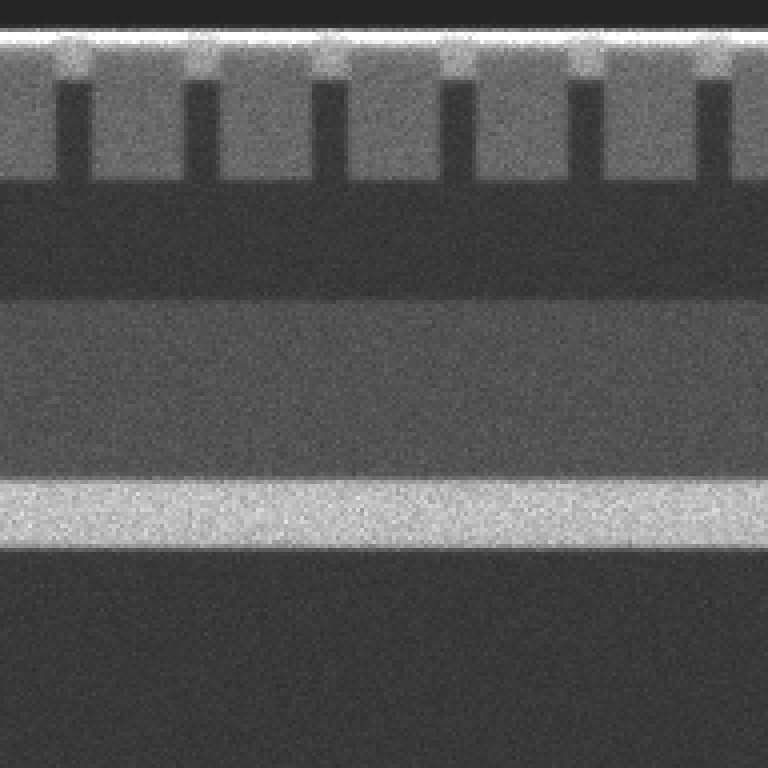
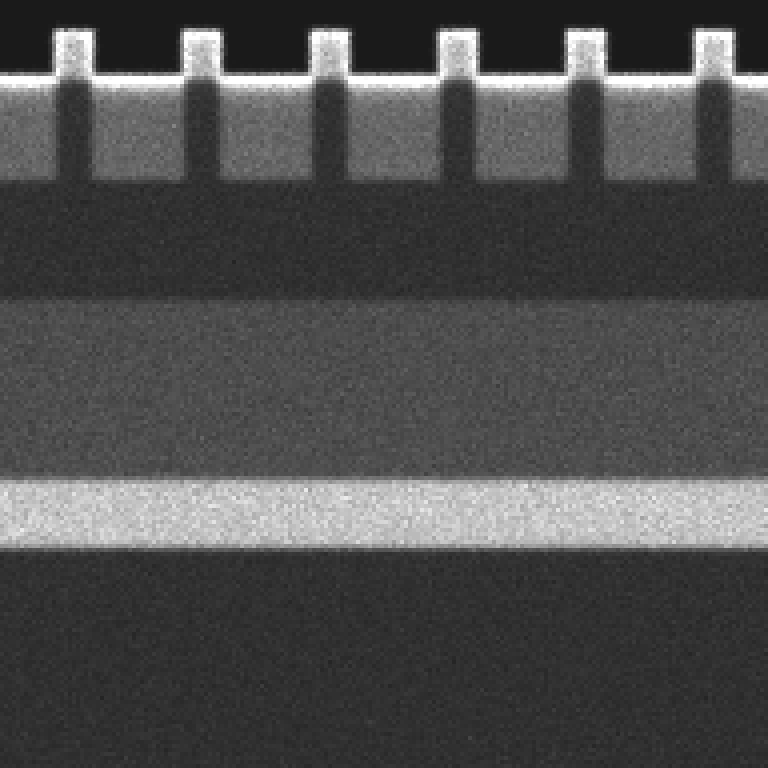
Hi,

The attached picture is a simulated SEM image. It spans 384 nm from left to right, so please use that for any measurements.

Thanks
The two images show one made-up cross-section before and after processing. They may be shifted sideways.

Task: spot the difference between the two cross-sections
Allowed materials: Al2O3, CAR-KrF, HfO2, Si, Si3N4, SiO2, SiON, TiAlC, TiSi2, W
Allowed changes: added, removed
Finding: removed SiO2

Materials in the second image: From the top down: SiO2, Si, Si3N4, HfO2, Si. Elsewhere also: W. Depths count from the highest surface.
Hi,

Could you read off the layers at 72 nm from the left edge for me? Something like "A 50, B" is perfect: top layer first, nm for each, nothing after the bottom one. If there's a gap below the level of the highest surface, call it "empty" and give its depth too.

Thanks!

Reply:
empty 22, SiO2 52, Si 60, Si3N4 90, HfO2 34, Si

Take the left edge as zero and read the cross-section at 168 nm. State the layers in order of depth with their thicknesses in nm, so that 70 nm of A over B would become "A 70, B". W 24, Si 110, Si3N4 90, HfO2 34, Si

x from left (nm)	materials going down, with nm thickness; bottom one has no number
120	empty 22, SiO2 52, Si 60, Si3N4 90, HfO2 34, Si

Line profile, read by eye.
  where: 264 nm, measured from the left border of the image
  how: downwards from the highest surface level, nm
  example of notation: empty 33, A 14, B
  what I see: empty 22, SiO2 52, Si 60, Si3N4 90, HfO2 34, Si